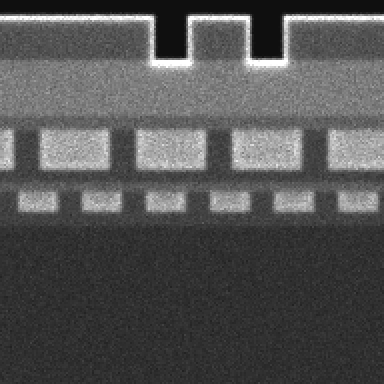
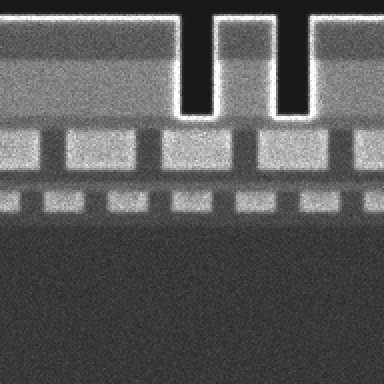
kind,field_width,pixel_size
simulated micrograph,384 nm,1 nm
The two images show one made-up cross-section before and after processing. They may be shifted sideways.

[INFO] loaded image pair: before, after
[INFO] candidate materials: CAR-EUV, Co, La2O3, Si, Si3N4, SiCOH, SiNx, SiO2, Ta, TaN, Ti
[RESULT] removed SiO2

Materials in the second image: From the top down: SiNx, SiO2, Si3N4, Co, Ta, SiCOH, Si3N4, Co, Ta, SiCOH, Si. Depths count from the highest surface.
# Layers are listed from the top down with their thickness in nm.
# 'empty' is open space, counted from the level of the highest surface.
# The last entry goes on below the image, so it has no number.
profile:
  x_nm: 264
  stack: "SiNx 44, SiO2 56, Si3N4 14, Ta 40, SiCOH 12, Si3N4 10, Co 12, Ta 8, SiCOH 14, Si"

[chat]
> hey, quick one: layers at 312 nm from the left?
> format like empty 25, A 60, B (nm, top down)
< SiNx 44, SiO2 56, Si3N4 14, Co 32, Ta 8, SiCOH 12, Si3N4 10, Co 12, Ta 8, SiCOH 14, Si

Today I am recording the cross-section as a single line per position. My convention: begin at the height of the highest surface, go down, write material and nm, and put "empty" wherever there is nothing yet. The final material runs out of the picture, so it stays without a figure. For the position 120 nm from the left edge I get SiNx 44, SiO2 56, Si3N4 14, Co 32, Ta 8, SiCOH 12, Si3N4 10, Co 12, Ta 8, SiCOH 14, Si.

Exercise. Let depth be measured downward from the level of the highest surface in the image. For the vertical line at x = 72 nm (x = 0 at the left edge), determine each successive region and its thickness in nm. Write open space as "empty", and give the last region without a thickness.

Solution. SiNx 44, SiO2 56, Si3N4 14, Ta 40, SiCOH 12, Si3N4 10, Co 12, Ta 8, SiCOH 14, Si